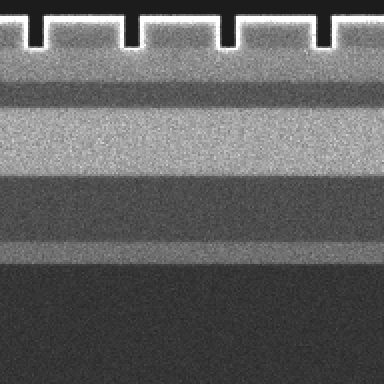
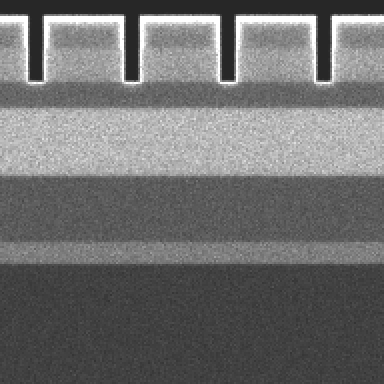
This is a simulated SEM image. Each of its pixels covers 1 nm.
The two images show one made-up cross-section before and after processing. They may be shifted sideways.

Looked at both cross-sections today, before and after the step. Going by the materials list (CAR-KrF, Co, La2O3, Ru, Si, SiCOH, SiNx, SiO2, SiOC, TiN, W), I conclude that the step removed Ru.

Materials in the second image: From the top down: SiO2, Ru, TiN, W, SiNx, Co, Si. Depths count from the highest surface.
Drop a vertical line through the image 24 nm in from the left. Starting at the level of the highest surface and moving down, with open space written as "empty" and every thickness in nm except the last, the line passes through SiO2 32, Ru 34, TiN 26, W 68, SiNx 66, Co 22, Si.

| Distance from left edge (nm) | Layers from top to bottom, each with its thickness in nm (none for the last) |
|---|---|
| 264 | SiO2 32, Ru 34, TiN 26, W 68, SiNx 66, Co 22, Si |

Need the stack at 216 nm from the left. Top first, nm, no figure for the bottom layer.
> SiO2 32, Ru 34, TiN 26, W 68, SiNx 66, Co 22, Si